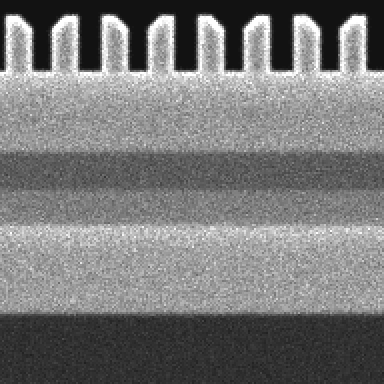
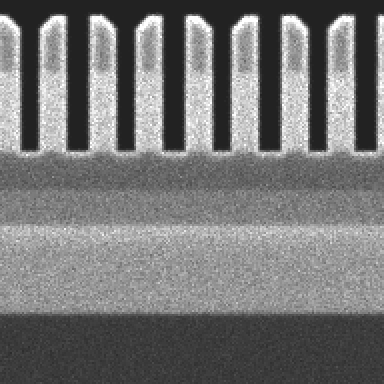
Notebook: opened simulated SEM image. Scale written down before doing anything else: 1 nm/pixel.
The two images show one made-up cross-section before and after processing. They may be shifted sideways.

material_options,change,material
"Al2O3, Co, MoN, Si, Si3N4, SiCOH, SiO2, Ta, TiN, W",removed,Co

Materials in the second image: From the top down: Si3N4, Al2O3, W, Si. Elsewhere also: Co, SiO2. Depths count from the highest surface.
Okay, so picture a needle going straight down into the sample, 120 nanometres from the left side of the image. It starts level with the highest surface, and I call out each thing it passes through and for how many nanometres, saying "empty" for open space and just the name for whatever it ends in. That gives empty 136, Si3N4 38, Al2O3 36, W 88, Si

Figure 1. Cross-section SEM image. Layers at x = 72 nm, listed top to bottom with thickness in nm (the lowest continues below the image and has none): empty 136, Si3N4 38, Al2O3 36, W 88, Si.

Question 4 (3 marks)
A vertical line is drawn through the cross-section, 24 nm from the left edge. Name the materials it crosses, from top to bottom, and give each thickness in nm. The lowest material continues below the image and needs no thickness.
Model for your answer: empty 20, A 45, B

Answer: empty 136, Si3N4 38, Al2O3 36, W 88, Si